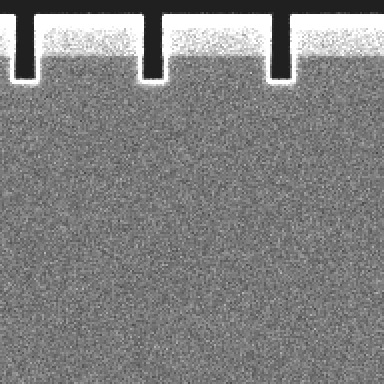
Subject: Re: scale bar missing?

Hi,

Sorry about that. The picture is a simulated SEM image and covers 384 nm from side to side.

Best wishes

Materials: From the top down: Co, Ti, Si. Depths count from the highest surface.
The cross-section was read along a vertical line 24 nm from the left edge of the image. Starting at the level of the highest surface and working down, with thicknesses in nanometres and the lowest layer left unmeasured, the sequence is empty 64, Si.